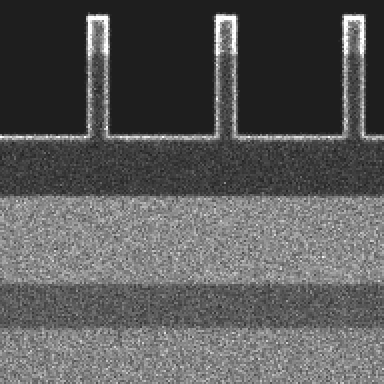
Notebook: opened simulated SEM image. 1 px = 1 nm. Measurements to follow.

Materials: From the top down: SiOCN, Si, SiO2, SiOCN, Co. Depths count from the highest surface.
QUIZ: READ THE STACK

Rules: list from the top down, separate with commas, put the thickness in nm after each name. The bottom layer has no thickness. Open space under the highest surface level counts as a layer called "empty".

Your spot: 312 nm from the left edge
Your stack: empty 120, Si 60, SiO2 88, SiOCN 44, Co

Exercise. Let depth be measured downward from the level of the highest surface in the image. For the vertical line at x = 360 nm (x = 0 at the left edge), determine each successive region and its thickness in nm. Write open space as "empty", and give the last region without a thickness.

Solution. SiOCN 38, Si 142, SiO2 88, SiOCN 44, Co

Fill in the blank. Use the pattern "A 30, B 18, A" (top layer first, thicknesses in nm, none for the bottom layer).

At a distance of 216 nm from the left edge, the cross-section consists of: SiOCN 38, Si 142, SiO2 88, SiOCN 44, Co